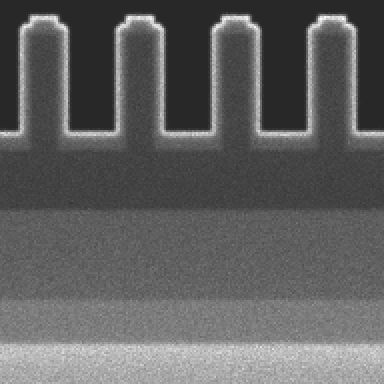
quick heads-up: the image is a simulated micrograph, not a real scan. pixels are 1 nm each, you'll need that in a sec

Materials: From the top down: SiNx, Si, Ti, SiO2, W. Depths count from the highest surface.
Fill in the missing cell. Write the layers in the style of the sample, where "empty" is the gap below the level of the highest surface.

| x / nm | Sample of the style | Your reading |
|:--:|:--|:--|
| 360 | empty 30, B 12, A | empty 116, SiNx 18, Si 60, Ti 90, SiO2 44, W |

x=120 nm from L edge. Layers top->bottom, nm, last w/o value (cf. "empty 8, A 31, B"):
empty 8, SiNx 126, Si 60, Ti 90, SiO2 44, W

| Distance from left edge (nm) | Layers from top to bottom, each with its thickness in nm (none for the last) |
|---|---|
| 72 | empty 116, SiNx 18, Si 60, Ti 90, SiO2 44, W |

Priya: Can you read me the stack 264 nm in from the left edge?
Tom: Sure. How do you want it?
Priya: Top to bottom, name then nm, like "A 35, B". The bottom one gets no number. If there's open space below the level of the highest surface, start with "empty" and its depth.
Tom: empty 116, SiNx 18, Si 60, Ti 90, SiO2 44, W